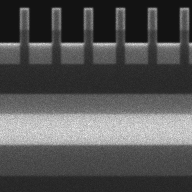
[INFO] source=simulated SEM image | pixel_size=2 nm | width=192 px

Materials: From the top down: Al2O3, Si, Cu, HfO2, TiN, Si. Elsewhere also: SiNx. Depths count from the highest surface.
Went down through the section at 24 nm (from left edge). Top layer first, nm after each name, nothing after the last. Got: empty 70, Al2O3 42, Si 60, Cu 40, HfO2 62, TiN 62, Si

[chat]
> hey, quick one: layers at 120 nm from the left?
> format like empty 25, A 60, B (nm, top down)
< SiNx 44, Si 128, Cu 40, HfO2 62, TiN 62, Si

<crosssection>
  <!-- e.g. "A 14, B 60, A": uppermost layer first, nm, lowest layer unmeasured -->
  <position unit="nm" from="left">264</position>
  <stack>empty 70, Al2O3 42, Si 60, Cu 40, HfO2 62, TiN 62, Si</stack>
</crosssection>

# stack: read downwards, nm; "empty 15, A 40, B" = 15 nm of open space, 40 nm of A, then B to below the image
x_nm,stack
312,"SiNx 44, Si 128, Cu 40, HfO2 62, TiN 62, Si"